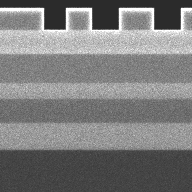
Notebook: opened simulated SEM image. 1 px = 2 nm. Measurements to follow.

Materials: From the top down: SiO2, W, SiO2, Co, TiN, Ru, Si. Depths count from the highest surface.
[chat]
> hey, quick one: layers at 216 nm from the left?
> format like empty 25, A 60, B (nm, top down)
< empty 44, W 48, SiO2 58, Co 32, TiN 48, Ru 54, Si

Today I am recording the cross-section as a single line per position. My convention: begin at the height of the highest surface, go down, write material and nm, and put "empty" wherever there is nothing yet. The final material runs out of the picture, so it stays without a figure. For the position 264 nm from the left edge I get SiO2 44, W 48, SiO2 58, Co 32, TiN 48, Ru 54, Si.